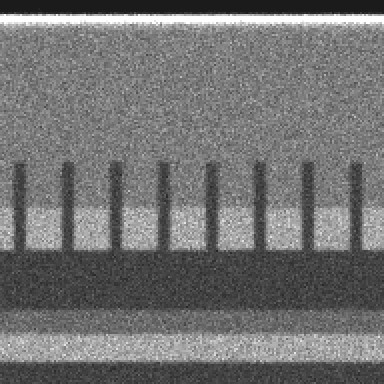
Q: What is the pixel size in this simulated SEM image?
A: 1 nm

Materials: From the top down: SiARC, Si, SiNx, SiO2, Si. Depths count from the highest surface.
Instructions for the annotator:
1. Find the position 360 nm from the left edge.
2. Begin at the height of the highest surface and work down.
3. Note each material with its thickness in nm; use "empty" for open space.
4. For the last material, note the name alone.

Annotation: SiARC 146, Si 148, SiNx 24, SiO2 28, Si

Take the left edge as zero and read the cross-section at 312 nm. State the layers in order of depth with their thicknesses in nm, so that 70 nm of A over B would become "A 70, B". SiARC 146, Si 148, SiNx 24, SiO2 28, Si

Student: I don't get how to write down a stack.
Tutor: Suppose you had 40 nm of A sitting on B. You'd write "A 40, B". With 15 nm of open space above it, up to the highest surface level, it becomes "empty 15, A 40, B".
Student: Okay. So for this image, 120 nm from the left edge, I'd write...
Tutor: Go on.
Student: SiARC 146, Si 148, SiNx 24, SiO2 28, Si